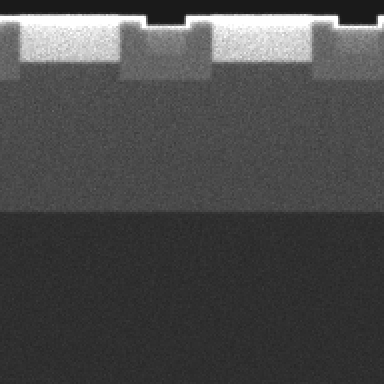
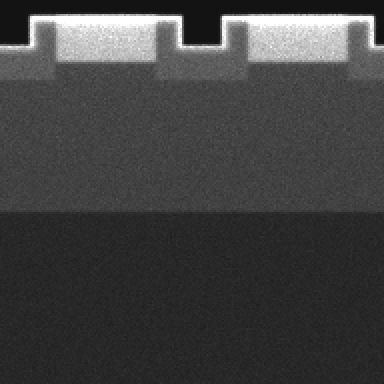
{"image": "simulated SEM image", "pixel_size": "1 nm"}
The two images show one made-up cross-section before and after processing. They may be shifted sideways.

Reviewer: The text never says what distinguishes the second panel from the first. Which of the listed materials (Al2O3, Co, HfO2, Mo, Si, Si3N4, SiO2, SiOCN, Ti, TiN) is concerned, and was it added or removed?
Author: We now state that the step removed Co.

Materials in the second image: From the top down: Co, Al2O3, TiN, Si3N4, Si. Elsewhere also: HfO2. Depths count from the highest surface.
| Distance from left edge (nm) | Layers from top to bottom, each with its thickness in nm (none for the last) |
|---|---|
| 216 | empty 30, Co 8, Al2O3 26, TiN 72, Si3N4 60, Si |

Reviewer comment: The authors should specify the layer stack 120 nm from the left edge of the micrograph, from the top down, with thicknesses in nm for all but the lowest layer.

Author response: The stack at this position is HfO2 46, TiN 90, Si3N4 60, Si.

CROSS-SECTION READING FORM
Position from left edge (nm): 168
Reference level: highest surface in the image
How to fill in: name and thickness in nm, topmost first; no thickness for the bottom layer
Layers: Al2O3 64, TiN 72, Si3N4 60, Si